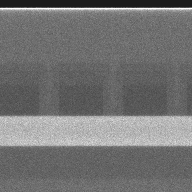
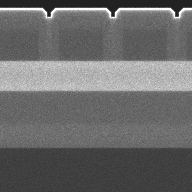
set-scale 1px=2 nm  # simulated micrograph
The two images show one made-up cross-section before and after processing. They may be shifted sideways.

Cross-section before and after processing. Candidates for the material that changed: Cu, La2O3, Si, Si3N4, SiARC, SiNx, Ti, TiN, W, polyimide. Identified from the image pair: TiN (removed).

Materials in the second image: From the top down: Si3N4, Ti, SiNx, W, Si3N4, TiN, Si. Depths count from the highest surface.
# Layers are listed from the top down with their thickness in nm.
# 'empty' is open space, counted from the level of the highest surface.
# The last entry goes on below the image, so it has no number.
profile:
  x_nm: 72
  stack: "Si3N4 16, Ti 28, SiNx 62, W 60, Si3N4 66, TiN 48, Si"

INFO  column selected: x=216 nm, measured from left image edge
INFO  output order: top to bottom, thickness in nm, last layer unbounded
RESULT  empty 4, Si3N4 102, W 60, Si3N4 66, TiN 48, Si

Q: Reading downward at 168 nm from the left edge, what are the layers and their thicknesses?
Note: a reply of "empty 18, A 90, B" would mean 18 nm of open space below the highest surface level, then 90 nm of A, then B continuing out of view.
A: Si3N4 16, Ti 28, SiNx 62, W 60, Si3N4 66, TiN 48, Si